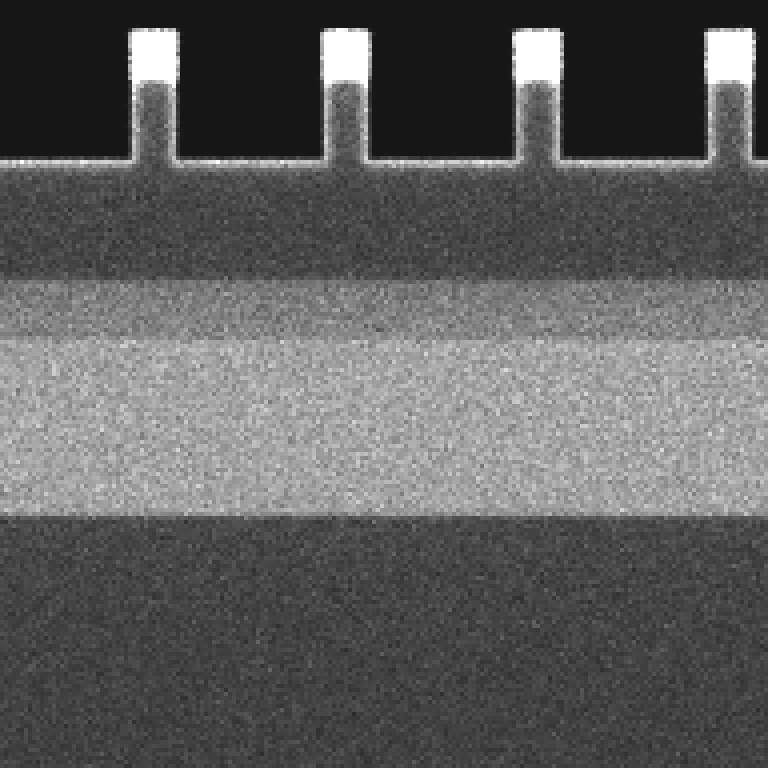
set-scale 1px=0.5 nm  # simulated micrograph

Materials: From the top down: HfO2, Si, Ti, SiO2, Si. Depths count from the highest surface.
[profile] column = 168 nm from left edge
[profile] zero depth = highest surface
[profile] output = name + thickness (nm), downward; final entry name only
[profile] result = HfO2 24, Si 100, Ti 30, SiO2 88, Si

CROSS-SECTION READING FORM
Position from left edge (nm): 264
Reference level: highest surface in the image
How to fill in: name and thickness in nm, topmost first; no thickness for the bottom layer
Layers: HfO2 24, Si 100, Ti 30, SiO2 88, Si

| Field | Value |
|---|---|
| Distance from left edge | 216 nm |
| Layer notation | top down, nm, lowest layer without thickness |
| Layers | empty 64, Si 60, Ti 30, SiO2 88, Si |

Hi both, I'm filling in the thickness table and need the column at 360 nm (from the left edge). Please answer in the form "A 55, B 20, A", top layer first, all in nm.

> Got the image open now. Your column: HfO2 24, Si 100, Ti 30, SiO2 88, Si